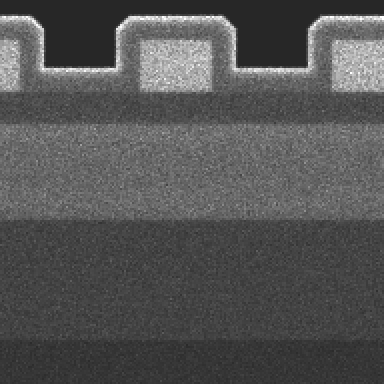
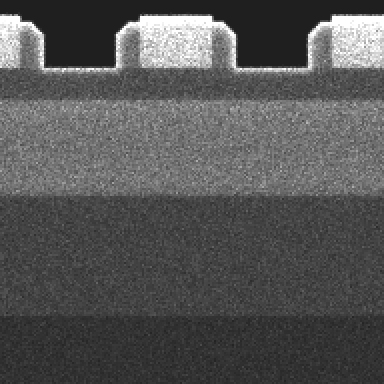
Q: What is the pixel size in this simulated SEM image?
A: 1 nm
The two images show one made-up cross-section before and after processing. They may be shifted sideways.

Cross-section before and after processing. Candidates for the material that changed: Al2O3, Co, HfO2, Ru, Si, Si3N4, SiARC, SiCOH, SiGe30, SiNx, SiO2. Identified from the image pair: Al2O3 (removed).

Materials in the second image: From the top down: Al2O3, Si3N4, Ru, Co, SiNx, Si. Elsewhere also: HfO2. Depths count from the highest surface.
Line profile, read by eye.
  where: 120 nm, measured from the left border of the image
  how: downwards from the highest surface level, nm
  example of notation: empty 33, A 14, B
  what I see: empty 14, Al2O3 38, Si3N4 32, Ru 86, Co 10, SiNx 120, Si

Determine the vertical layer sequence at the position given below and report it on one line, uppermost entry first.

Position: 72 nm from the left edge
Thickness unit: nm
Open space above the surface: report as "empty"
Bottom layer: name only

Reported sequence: empty 52, Si3N4 32, Ru 86, Co 10, SiNx 120, Si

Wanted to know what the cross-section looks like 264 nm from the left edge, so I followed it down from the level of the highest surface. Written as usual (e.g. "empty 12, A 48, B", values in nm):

empty 52, Si3N4 32, Ru 86, Co 10, SiNx 120, Si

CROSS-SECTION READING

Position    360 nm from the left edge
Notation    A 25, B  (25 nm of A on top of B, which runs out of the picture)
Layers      HfO2 52, Si3N4 32, Ru 86, Co 10, SiNx 120, Si